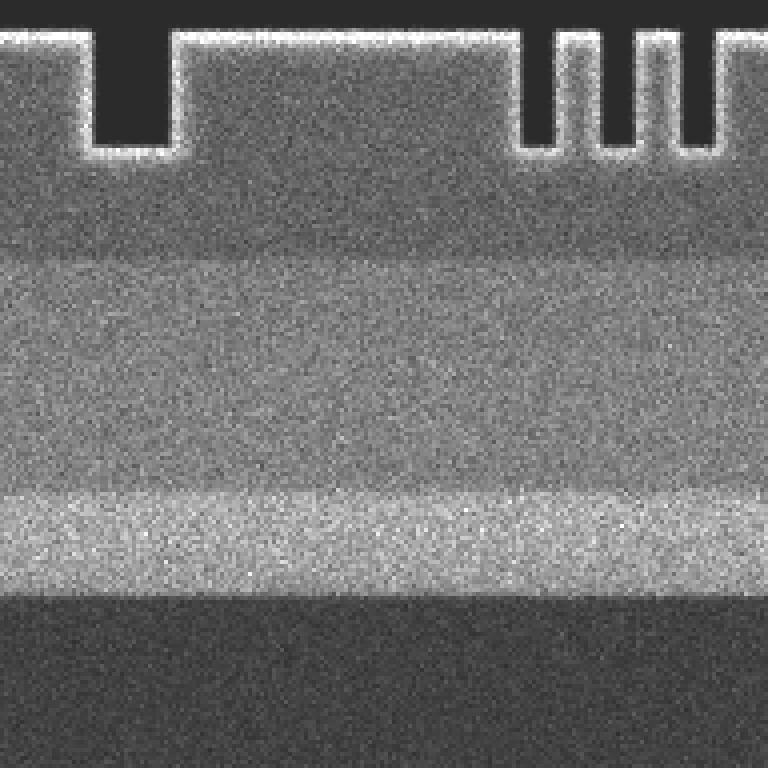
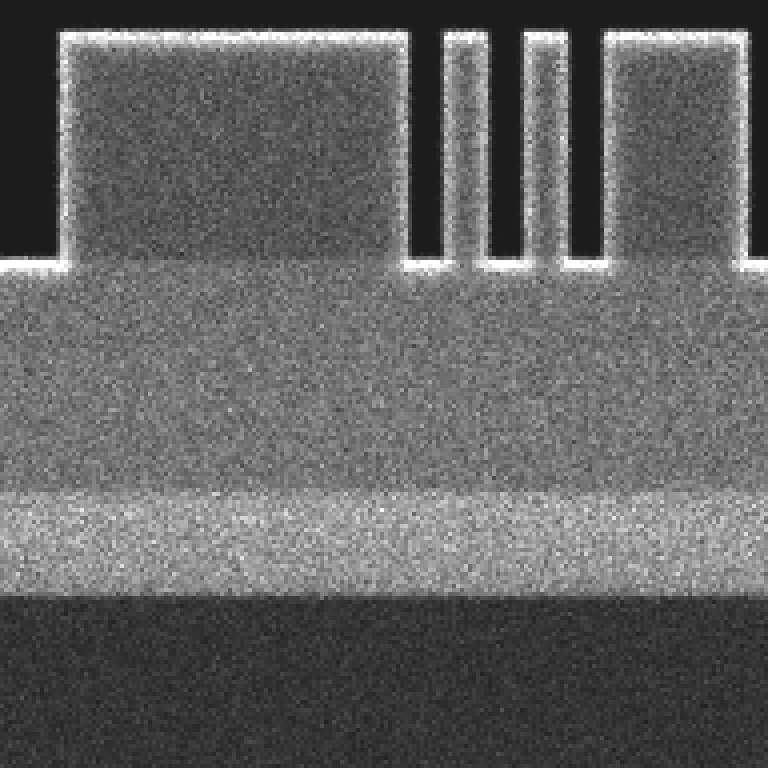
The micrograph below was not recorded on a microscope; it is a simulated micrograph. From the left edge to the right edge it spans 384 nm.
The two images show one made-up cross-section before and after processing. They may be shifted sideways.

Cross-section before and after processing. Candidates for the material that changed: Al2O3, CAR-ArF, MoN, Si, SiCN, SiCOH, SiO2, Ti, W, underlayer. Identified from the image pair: underlayer (removed).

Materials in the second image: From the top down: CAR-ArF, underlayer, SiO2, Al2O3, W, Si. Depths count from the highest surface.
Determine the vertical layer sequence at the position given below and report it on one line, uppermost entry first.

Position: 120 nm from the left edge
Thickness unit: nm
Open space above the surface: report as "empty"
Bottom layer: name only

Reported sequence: CAR-ArF 58, underlayer 56, SiO2 44, Al2O3 72, W 52, Si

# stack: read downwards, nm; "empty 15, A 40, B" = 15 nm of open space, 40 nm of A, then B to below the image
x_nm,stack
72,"CAR-ArF 58, underlayer 56, SiO2 44, Al2O3 72, W 52, Si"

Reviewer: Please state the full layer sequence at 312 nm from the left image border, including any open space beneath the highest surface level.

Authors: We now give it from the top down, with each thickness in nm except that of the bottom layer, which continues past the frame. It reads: CAR-ArF 58, underlayer 56, SiO2 44, Al2O3 72, W 52, Si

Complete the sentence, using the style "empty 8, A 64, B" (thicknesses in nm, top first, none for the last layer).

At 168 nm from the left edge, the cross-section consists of CAR-ArF 58, underlayer 56, SiO2 44, Al2O3 72, W 52, Si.